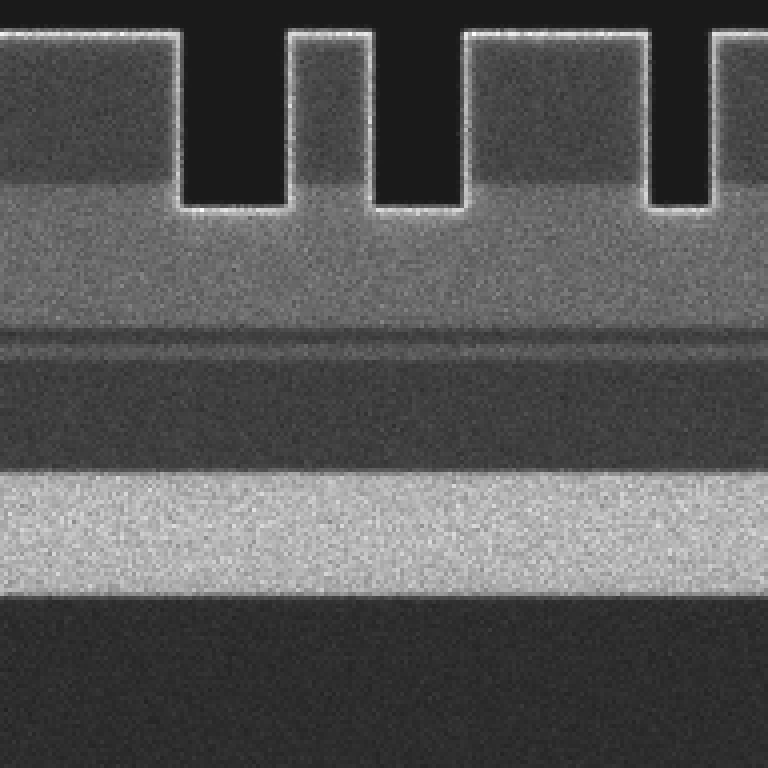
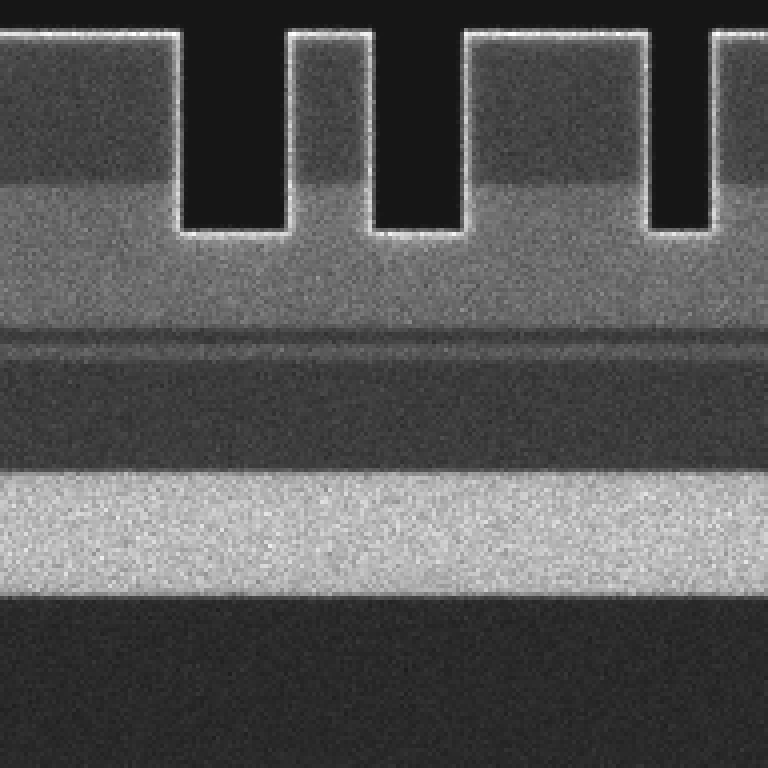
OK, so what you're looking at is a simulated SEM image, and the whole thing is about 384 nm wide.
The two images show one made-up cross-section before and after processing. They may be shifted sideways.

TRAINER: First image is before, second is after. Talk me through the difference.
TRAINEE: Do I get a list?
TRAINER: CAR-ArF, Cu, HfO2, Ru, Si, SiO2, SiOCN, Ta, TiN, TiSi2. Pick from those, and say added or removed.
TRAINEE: removed: Ru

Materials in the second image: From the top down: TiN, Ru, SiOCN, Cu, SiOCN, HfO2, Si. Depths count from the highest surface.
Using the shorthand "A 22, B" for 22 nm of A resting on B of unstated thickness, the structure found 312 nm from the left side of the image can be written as TiN 76, Ru 72, SiOCN 8, Cu 8, SiOCN 56, HfO2 62, Si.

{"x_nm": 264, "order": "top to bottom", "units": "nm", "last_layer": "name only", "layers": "TiN 76, Ru 72, SiOCN 8, Cu 8, SiOCN 56, HfO2 62, Si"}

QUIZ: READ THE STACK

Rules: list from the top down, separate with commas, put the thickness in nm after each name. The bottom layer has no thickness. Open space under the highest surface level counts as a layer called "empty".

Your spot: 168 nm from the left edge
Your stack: TiN 76, Ru 72, SiOCN 8, Cu 8, SiOCN 56, HfO2 62, Si